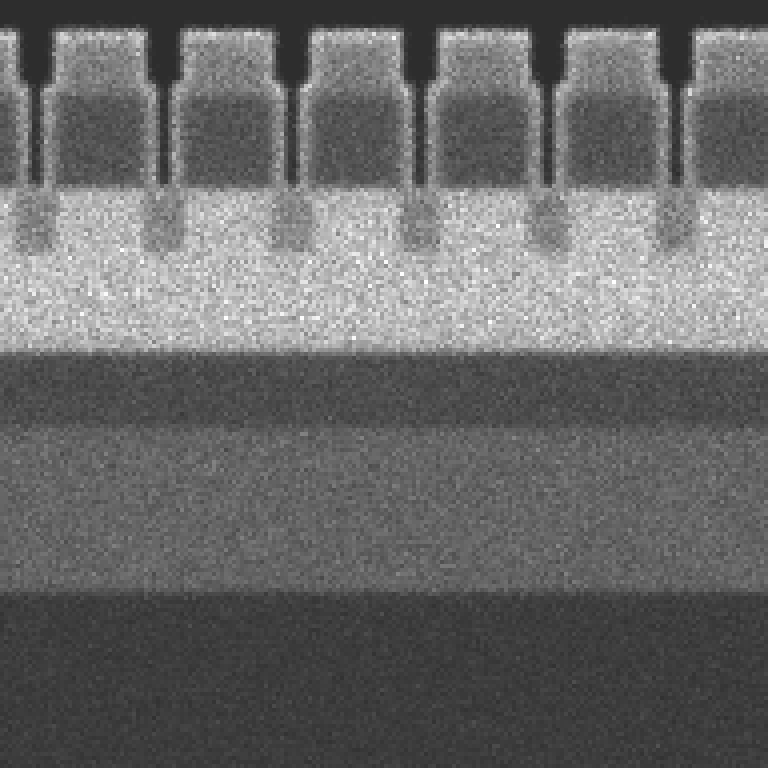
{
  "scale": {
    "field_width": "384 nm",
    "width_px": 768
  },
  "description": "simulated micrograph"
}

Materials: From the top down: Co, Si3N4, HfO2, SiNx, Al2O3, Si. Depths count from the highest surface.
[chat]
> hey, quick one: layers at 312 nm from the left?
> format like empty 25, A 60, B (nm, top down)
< Co 32, Si3N4 46, HfO2 82, SiNx 38, Al2O3 82, Si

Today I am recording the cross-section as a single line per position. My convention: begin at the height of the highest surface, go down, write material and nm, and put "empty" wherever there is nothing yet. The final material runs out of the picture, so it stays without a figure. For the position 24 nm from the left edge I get empty 26, Co 84, HfO2 50, SiNx 38, Al2O3 82, Si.